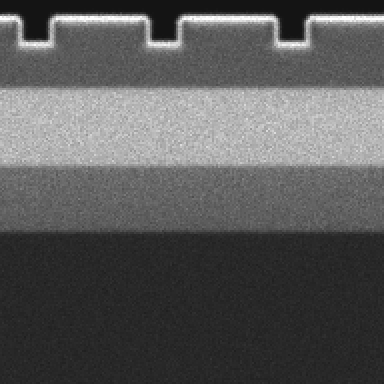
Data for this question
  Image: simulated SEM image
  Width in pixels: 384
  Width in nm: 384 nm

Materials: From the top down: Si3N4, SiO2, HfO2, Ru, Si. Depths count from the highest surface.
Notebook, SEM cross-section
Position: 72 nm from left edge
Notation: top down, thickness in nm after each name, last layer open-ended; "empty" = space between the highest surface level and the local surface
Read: SiO2 72, HfO2 78, Ru 66, Si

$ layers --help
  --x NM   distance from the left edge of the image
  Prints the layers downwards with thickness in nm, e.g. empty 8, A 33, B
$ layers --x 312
Si3N4 26, SiO2 46, HfO2 78, Ru 66, Si